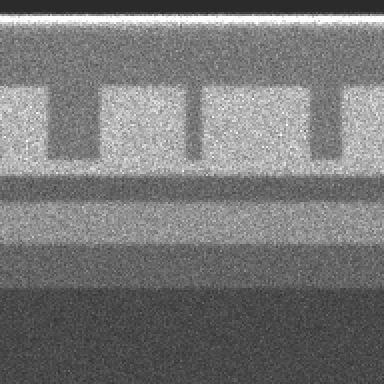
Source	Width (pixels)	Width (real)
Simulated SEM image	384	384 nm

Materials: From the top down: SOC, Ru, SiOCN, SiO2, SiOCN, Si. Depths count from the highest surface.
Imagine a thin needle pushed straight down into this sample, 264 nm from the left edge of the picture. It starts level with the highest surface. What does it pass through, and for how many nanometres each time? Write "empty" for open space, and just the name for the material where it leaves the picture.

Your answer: SOC 70, Ru 90, SiOCN 26, SiO2 42, SiOCN 44, Si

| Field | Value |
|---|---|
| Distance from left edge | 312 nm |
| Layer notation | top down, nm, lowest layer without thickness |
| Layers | SOC 144, Ru 16, SiOCN 26, SiO2 42, SiOCN 44, Si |